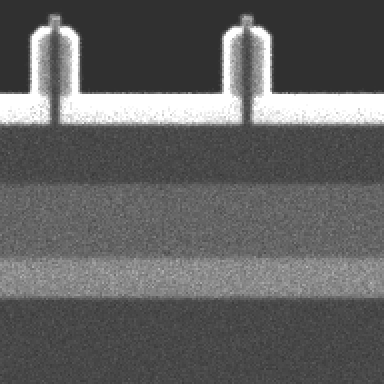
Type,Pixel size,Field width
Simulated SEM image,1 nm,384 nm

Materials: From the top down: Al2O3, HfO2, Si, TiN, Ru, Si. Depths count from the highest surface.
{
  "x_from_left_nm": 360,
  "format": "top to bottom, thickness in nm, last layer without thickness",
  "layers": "empty 80, HfO2 28, Si 60, TiN 74, Ru 40, Si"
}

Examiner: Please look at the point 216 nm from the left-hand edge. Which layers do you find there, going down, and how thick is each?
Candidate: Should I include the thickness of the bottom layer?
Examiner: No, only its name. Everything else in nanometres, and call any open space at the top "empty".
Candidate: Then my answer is empty 80, HfO2 28, Si 60, TiN 74, Ru 40, Si